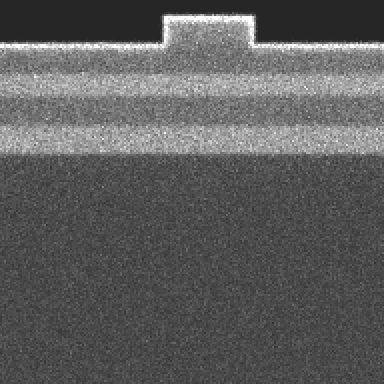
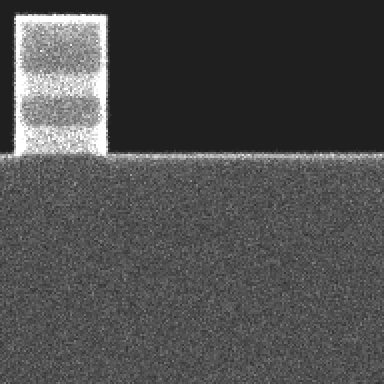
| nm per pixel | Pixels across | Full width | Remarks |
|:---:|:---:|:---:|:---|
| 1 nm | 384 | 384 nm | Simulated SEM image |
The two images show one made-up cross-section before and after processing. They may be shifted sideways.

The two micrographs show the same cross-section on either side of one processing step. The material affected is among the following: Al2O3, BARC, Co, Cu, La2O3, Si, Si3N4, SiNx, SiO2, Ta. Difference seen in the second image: Al2O3 and SiNx removed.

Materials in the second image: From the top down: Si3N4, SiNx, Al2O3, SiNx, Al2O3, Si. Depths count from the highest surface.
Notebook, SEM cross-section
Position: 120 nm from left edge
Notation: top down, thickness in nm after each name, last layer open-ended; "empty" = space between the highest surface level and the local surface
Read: empty 138, Si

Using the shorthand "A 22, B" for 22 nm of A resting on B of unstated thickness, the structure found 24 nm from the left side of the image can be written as Si3N4 28, SiNx 30, Al2O3 22, SiNx 30, Al2O3 28, Si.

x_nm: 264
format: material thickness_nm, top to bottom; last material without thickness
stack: empty 138, Si